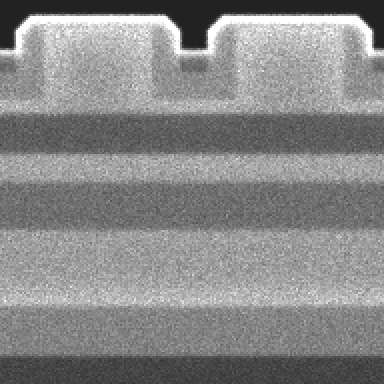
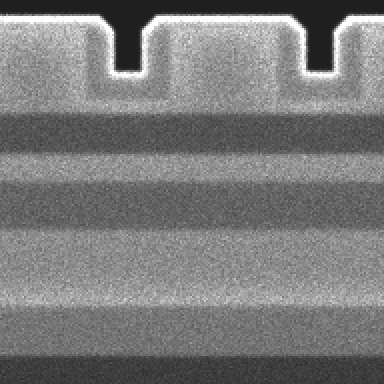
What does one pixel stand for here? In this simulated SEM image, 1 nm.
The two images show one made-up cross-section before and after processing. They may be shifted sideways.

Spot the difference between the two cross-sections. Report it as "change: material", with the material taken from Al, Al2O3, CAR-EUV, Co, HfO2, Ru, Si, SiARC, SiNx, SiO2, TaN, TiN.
removed: SiARC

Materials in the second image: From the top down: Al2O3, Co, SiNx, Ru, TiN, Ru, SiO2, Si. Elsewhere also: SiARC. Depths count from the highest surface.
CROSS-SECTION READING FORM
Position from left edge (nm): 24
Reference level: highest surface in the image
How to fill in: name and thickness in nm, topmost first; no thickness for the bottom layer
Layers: Al2O3 12, Co 86, SiNx 40, Ru 28, TiN 48, Ru 76, SiO2 50, Si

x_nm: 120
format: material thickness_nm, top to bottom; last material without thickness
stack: empty 56, Al2O3 28, Co 14, SiNx 40, Ru 28, TiN 48, Ru 76, SiO2 50, Si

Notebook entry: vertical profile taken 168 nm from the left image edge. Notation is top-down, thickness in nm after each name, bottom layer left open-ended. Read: Al2O3 84, Co 14, SiNx 40, Ru 28, TiN 48, Ru 76, SiO2 50, Si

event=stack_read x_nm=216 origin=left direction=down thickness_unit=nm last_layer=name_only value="Al2O3 12, Co 86, SiNx 40, Ru 28, TiN 48, Ru 76, SiO2 50, Si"